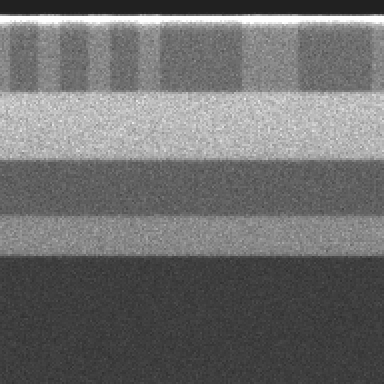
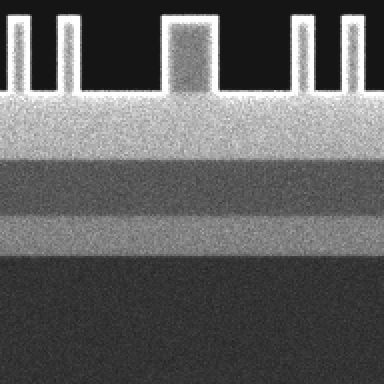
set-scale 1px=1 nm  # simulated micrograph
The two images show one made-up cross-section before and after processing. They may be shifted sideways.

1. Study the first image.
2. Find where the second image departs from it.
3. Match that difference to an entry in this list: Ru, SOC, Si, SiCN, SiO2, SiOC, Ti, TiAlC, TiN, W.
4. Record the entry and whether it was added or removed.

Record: SOC / removed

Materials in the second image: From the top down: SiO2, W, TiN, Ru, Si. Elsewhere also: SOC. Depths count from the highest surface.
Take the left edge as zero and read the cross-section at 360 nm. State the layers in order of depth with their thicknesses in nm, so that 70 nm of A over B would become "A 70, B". SiO2 76, W 68, TiN 56, Ru 40, Si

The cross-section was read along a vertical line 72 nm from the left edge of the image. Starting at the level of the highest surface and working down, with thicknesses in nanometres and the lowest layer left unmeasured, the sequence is SiO2 76, W 68, TiN 56, Ru 40, Si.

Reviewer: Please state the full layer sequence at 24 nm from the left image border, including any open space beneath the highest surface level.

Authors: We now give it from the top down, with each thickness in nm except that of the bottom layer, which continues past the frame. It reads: SiO2 76, W 68, TiN 56, Ru 40, Si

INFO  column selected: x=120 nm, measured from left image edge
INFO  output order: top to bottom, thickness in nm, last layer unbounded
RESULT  empty 76, W 68, TiN 56, Ru 40, Si